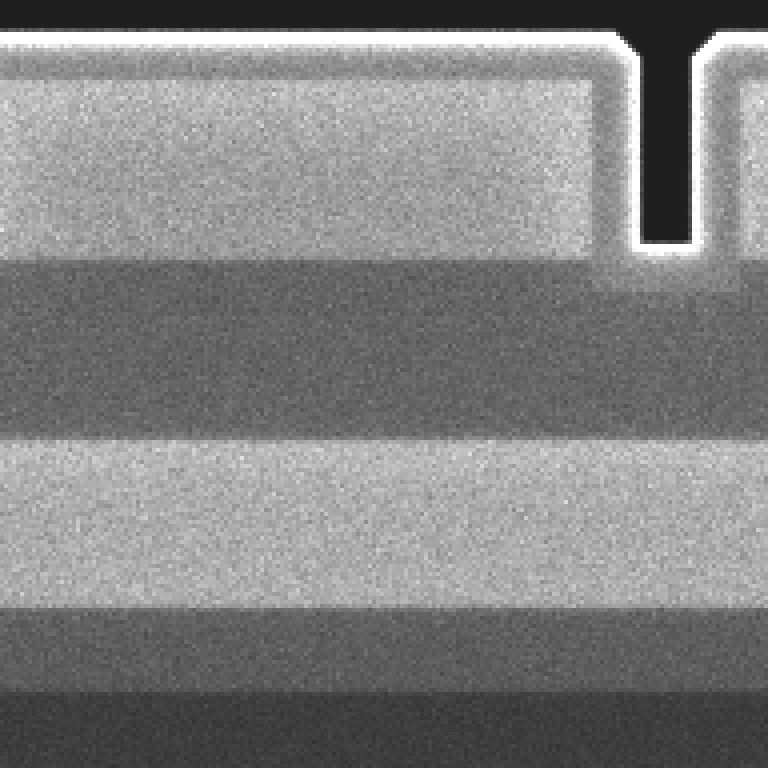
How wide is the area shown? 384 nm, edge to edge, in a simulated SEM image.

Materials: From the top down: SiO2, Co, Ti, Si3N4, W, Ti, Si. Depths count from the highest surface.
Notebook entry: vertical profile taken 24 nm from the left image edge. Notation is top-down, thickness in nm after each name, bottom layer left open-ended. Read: SiO2 24, Co 90, Ti 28, Si3N4 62, W 84, Ti 42, Si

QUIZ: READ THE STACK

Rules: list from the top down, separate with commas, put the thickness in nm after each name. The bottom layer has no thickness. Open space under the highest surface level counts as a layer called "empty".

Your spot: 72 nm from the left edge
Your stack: SiO2 24, Co 90, Ti 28, Si3N4 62, W 84, Ti 42, Si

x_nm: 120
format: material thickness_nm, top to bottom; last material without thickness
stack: SiO2 24, Co 90, Ti 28, Si3N4 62, W 84, Ti 42, Si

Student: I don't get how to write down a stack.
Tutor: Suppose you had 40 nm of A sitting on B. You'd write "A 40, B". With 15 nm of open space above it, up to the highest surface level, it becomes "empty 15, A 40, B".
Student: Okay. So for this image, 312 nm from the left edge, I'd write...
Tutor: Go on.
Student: empty 6, SiO2 124, Ti 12, Si3N4 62, W 84, Ti 42, Si